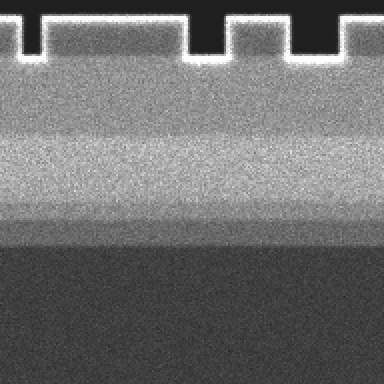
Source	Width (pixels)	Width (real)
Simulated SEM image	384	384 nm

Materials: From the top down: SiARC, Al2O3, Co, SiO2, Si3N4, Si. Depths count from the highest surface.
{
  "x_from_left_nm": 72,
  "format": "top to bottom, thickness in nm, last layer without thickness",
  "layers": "SiARC 40, Al2O3 80, Co 66, SiO2 18, Si3N4 26, Si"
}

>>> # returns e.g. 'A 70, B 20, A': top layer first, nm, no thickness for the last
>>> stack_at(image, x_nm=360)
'SiARC 40, Al2O3 80, Co 66, SiO2 18, Si3N4 26, Si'